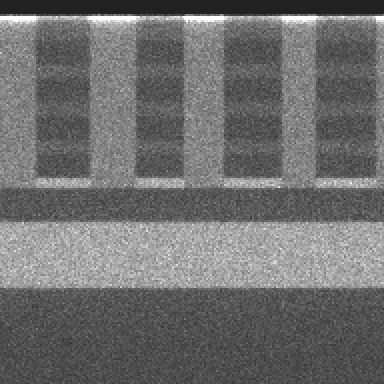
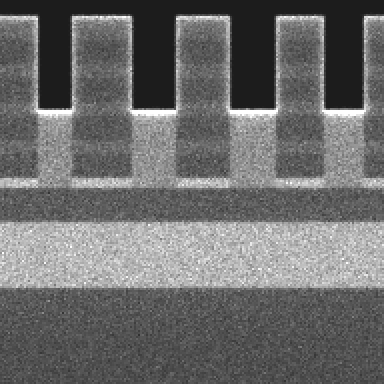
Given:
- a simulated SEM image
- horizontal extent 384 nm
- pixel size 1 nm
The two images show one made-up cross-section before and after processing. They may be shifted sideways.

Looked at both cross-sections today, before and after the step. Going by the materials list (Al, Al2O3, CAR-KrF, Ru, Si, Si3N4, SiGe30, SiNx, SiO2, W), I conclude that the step removed Si3N4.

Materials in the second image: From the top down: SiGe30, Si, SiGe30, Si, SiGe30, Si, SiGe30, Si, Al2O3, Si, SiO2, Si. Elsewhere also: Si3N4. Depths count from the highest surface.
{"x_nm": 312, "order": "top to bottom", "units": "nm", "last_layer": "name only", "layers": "SiGe30 24, Si 24, SiGe30 14, Si 24, SiGe30 14, Si 24, SiGe30 14, Si 24, Al2O3 10, Si 34, SiO2 66, Si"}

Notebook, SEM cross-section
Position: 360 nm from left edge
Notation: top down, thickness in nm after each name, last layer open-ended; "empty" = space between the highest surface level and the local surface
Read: empty 94, Si3N4 78, Si 34, SiO2 66, Si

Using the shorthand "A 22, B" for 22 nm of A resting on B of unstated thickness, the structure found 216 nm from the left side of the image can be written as SiGe30 24, Si 24, SiGe30 14, Si 24, SiGe30 14, Si 24, SiGe30 14, Si 24, Al2O3 10, Si 34, SiO2 66, Si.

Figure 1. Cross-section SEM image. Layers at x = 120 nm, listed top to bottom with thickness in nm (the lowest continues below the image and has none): SiGe30 24, Si 24, SiGe30 14, Si 24, SiGe30 14, Si 24, SiGe30 14, Si 24, Al2O3 10, Si 34, SiO2 66, Si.